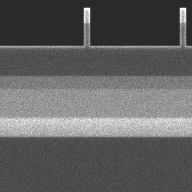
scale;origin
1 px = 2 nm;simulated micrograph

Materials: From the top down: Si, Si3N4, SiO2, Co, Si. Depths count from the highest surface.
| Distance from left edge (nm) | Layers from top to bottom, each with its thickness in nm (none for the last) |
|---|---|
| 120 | empty 76, Si 60, Si3N4 26, SiO2 58, Co 38, Si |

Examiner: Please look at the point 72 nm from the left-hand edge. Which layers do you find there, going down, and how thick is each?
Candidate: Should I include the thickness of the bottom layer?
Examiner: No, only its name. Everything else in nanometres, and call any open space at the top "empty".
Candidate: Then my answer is empty 76, Si 60, Si3N4 26, SiO2 58, Co 38, Si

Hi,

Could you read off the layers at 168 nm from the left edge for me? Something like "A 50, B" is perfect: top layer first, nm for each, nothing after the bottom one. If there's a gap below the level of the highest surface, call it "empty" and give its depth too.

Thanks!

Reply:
Si 136, Si3N4 26, SiO2 58, Co 38, Si